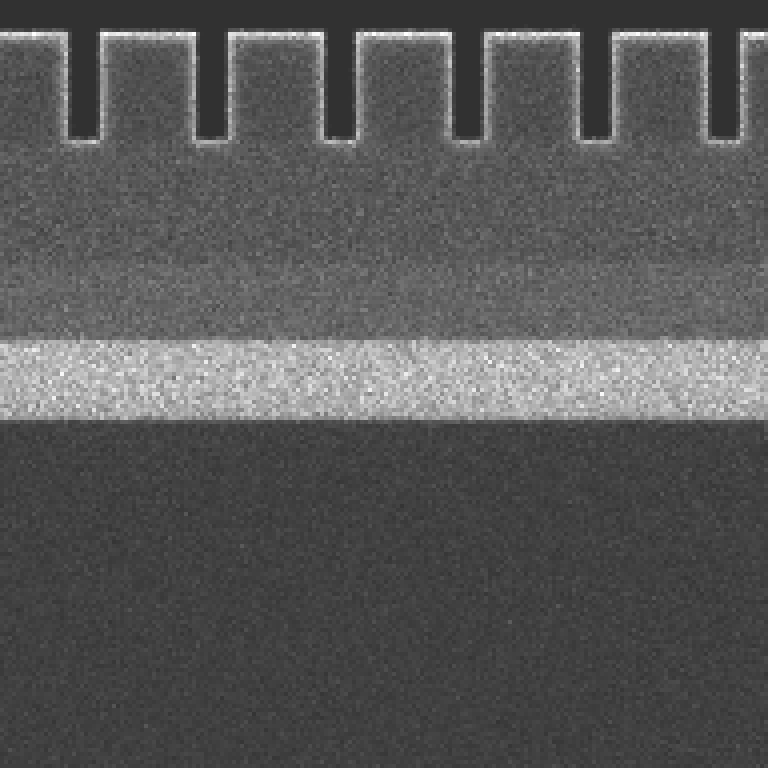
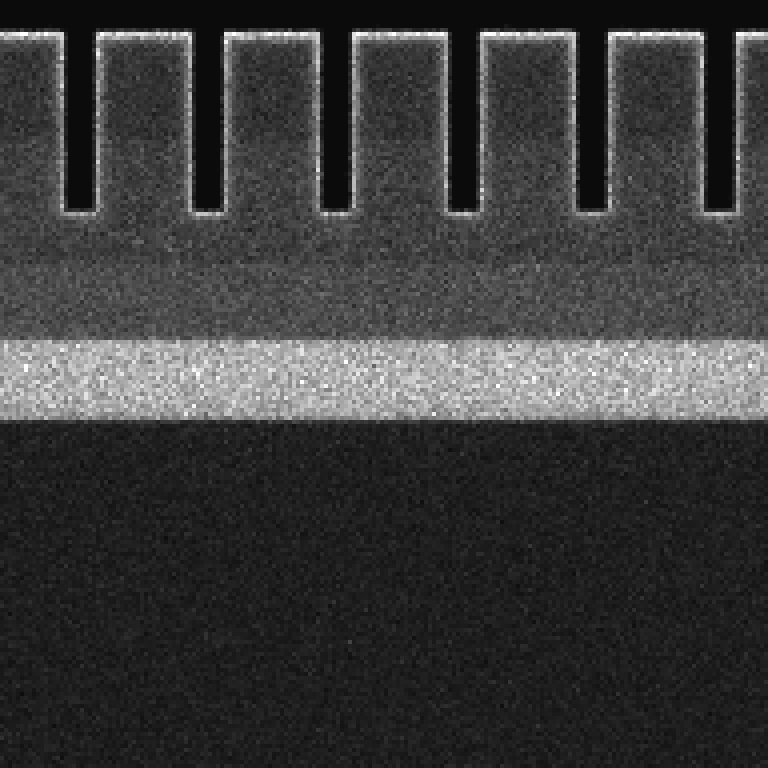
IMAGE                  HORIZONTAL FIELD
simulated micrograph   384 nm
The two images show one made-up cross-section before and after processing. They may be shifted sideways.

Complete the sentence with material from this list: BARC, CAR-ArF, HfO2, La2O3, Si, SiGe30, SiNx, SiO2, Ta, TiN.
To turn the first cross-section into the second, TiN must be removed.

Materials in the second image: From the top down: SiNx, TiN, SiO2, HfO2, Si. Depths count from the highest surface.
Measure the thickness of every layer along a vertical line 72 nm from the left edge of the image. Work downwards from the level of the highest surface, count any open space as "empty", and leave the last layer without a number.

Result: SiNx 54, TiN 62, SiO2 38, HfO2 40, Si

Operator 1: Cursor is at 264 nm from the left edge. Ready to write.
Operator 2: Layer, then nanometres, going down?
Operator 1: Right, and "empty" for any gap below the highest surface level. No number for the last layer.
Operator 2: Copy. SiNx 54, TiN 62, SiO2 38, HfO2 40, Si